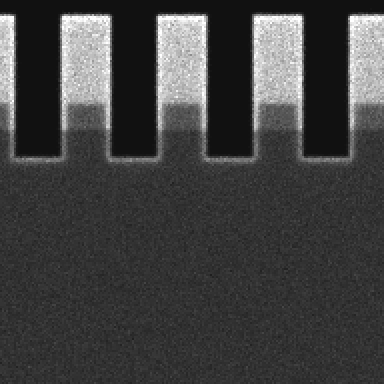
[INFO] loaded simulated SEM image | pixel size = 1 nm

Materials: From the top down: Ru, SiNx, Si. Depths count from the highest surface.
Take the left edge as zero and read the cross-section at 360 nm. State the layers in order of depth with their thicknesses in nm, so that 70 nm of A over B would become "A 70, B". Ru 88, SiNx 26, Si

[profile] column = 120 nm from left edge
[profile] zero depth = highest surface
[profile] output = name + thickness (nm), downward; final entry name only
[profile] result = empty 142, Si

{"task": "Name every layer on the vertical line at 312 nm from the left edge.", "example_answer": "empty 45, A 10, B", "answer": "empty 142, Si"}